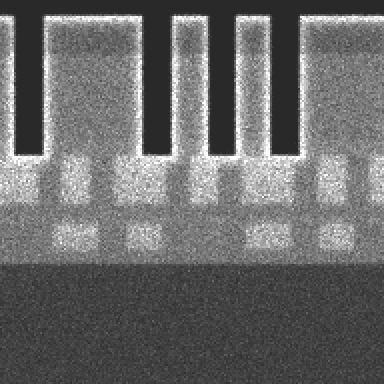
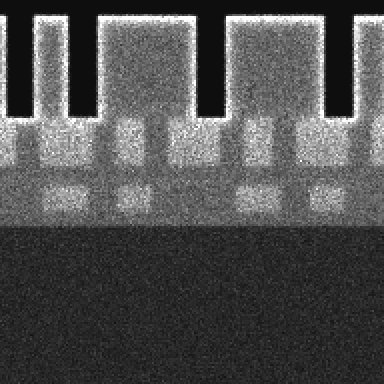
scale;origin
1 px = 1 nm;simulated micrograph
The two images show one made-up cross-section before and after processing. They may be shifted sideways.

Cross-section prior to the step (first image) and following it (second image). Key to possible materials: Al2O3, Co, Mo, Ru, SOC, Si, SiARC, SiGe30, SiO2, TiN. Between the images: SOC was removed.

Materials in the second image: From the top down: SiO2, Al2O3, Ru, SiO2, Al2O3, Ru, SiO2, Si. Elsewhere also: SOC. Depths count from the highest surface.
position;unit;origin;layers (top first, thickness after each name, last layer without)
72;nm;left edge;empty 102, Ru 48, SiO2 12, Al2O3 8, Ru 26, SiO2 14, Si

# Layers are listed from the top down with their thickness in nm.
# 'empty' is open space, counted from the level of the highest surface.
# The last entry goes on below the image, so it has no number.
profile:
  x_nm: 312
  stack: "SiO2 86, Al2O3 16, Ru 48, SiO2 12, Al2O3 8, Ru 26, SiO2 14, Si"